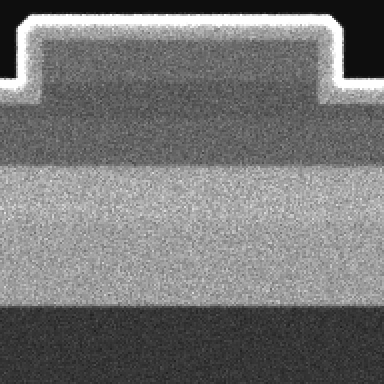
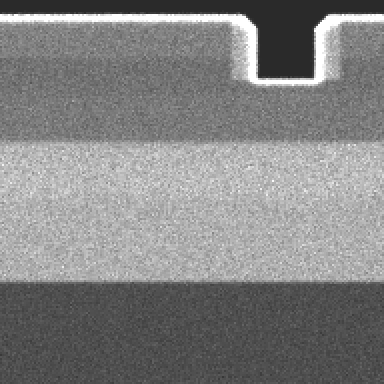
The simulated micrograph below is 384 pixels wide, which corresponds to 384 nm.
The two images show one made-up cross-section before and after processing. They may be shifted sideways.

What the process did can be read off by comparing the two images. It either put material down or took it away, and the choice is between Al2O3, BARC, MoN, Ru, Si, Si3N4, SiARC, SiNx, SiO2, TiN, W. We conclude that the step removed SiO2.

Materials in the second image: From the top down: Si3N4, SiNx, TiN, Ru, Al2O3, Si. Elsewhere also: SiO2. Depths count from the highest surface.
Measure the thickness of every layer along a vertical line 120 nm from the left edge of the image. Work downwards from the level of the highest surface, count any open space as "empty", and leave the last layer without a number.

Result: Si3N4 42, SiNx 36, TiN 48, Ru 56, Al2O3 84, Si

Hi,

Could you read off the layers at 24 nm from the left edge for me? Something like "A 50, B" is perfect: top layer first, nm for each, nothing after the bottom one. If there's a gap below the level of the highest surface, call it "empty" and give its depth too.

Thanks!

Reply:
Si3N4 42, SiNx 36, TiN 48, Ru 56, Al2O3 84, Si